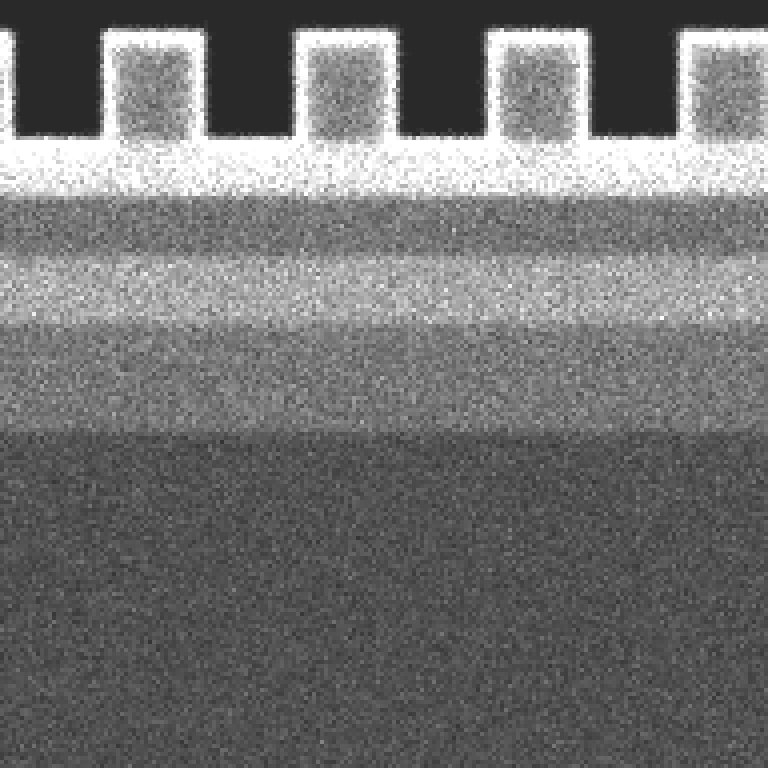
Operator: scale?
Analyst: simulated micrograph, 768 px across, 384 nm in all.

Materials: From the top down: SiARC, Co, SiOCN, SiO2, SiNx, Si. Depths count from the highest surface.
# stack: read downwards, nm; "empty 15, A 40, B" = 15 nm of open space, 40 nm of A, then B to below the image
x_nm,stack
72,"SiARC 54, Co 28, SiOCN 30, SiO2 34, SiNx 54, Si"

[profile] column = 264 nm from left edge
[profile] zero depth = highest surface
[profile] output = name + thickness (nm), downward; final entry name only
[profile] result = SiARC 54, Co 28, SiOCN 30, SiO2 34, SiNx 54, Si